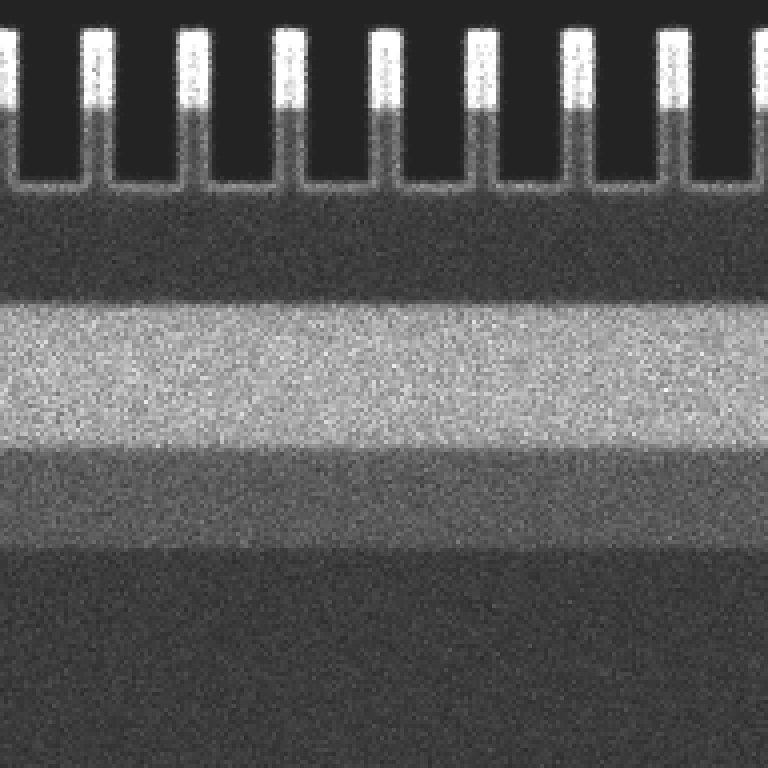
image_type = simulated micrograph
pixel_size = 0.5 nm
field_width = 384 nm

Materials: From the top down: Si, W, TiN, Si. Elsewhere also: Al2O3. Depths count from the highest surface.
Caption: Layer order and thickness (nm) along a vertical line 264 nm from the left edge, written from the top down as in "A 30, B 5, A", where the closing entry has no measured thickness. empty 76, Si 60, W 72, TiN 50, Si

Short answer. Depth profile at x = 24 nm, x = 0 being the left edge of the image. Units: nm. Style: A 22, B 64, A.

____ empty 76, Si 60, W 72, TiN 50, Si